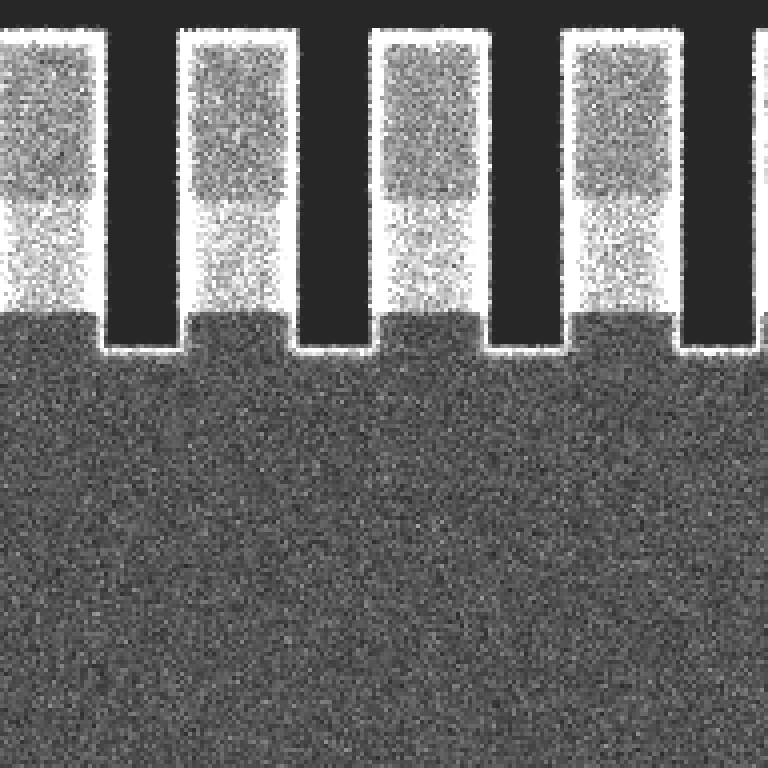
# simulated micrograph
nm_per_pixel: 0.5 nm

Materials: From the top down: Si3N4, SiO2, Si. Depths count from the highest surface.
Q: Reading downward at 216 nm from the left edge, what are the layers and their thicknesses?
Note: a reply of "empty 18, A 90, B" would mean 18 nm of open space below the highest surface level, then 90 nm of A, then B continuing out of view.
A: Si3N4 84, SiO2 56, Si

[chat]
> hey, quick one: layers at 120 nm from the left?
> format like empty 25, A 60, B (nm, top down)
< Si3N4 84, SiO2 56, Si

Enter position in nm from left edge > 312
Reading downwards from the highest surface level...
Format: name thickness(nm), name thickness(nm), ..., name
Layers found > Si3N4 84, SiO2 56, Si